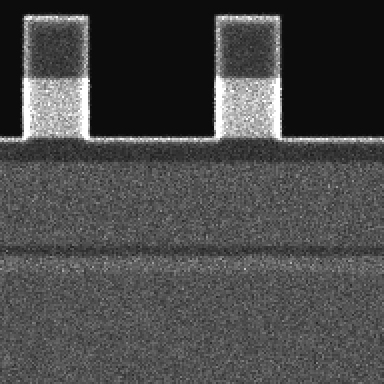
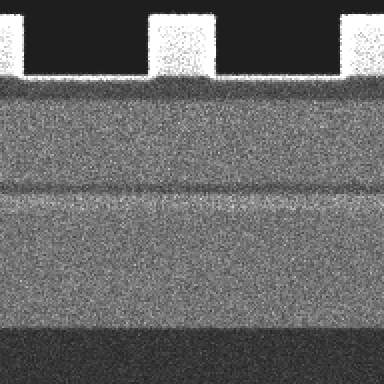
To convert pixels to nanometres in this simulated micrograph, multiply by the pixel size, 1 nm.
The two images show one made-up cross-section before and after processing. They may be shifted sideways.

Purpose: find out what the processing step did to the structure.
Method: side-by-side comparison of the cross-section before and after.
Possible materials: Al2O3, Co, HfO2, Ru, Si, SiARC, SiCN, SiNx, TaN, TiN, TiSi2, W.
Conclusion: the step removed SiARC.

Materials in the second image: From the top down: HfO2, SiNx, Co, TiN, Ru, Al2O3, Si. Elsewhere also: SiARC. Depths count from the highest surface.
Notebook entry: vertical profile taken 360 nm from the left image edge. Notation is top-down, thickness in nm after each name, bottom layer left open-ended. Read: HfO2 60, SiNx 24, Co 84, TiN 10, Ru 16, Al2O3 118, Si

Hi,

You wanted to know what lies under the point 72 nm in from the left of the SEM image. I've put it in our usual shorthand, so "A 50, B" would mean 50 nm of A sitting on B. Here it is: empty 60, SiNx 24, Co 84, TiN 10, Ru 16, Al2O3 118, Si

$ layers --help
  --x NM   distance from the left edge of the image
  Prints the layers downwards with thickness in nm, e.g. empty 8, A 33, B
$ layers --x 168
HfO2 60, SiNx 24, Co 84, TiN 10, Ru 16, Al2O3 118, Si